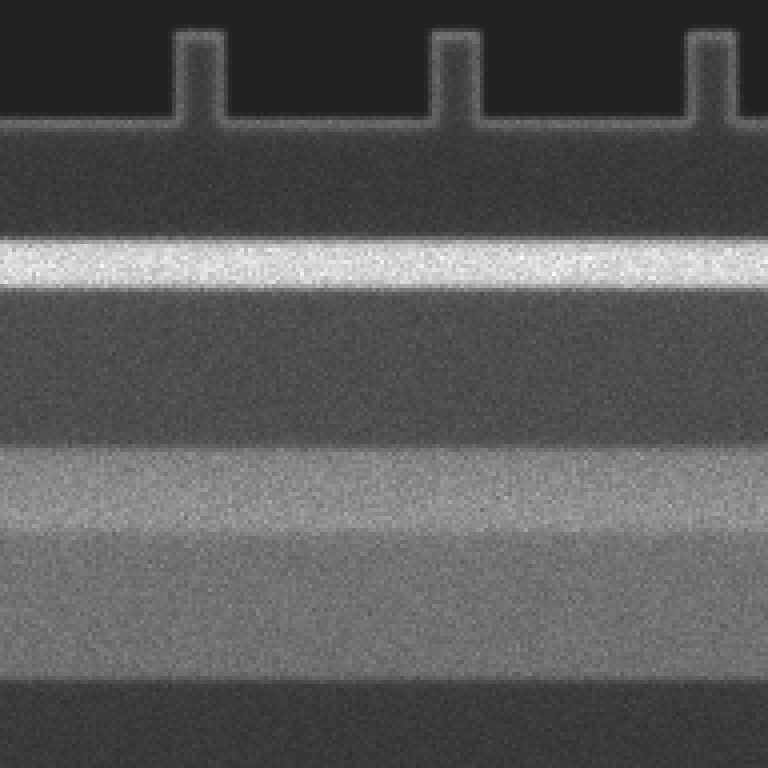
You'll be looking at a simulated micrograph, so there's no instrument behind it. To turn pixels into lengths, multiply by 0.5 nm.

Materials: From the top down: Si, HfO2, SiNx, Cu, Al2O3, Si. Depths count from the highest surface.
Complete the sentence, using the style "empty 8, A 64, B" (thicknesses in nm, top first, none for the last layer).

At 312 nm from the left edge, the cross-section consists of empty 44, Si 60, HfO2 24, SiNx 80, Cu 42, Al2O3 74, Si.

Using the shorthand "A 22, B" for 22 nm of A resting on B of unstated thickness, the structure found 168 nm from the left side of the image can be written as empty 44, Si 60, HfO2 24, SiNx 80, Cu 42, Al2O3 74, Si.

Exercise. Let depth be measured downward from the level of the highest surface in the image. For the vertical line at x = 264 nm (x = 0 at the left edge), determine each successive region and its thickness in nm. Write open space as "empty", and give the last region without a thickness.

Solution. empty 44, Si 60, HfO2 24, SiNx 80, Cu 42, Al2O3 74, Si